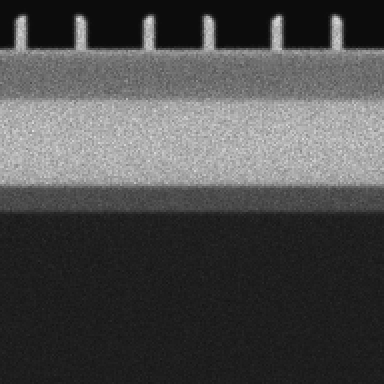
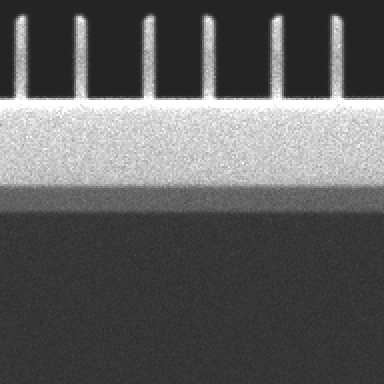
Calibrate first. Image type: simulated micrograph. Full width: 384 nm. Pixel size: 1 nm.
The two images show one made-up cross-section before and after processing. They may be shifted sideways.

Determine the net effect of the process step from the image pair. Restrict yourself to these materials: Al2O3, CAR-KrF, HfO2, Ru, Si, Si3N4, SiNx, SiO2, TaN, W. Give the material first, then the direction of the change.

Ru: removed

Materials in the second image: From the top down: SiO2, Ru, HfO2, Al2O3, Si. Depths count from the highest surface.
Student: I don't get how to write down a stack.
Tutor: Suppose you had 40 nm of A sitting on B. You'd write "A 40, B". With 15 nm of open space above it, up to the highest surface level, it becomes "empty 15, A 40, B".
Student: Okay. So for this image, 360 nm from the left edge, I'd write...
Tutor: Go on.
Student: empty 84, HfO2 86, Al2O3 26, Si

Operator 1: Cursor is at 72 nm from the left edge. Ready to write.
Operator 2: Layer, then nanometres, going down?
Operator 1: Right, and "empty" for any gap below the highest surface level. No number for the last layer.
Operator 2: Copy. empty 84, HfO2 86, Al2O3 26, Si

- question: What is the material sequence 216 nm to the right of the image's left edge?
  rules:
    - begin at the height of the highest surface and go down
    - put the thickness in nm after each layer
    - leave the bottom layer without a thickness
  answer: empty 84, HfO2 86, Al2O3 26, Si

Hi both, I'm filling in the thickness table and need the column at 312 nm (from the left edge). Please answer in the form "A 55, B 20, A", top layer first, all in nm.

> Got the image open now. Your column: empty 84, HfO2 86, Al2O3 26, Si